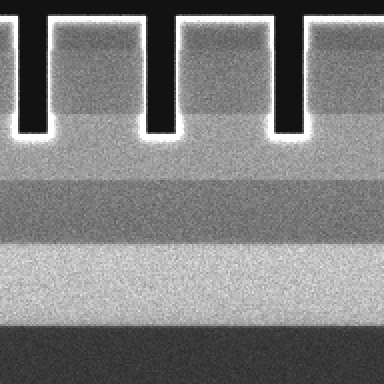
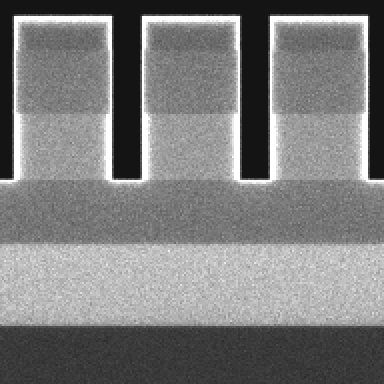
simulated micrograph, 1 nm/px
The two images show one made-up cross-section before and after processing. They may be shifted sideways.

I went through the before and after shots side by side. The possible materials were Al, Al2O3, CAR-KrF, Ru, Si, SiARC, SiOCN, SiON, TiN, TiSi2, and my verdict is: removed, Al2O3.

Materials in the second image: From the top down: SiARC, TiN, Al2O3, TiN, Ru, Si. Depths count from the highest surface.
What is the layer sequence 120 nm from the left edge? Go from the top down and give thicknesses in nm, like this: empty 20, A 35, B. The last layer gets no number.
empty 164, TiN 64, Ru 82, Si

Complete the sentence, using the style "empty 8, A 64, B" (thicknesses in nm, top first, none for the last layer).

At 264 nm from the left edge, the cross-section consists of empty 164, TiN 64, Ru 82, Si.